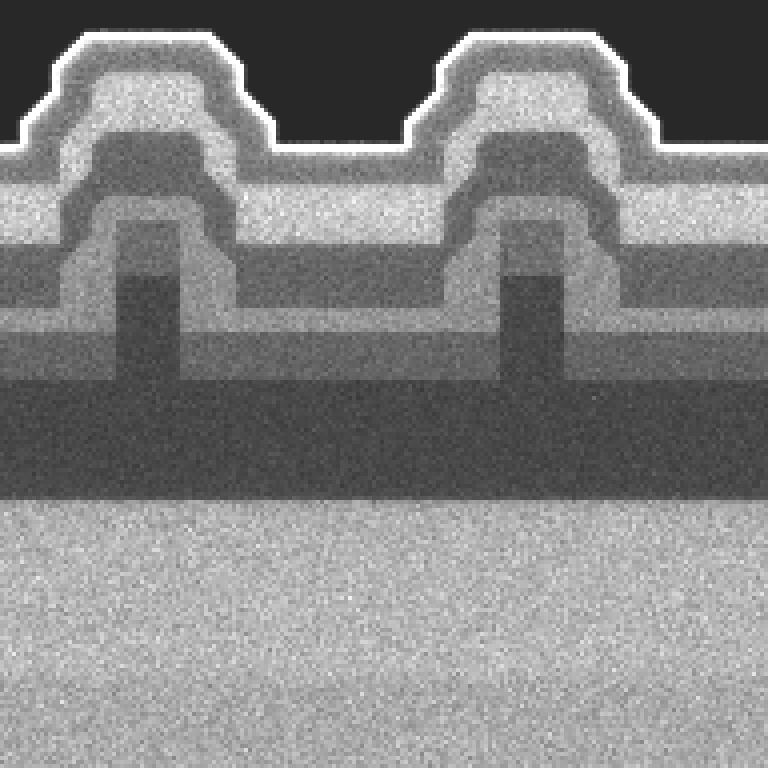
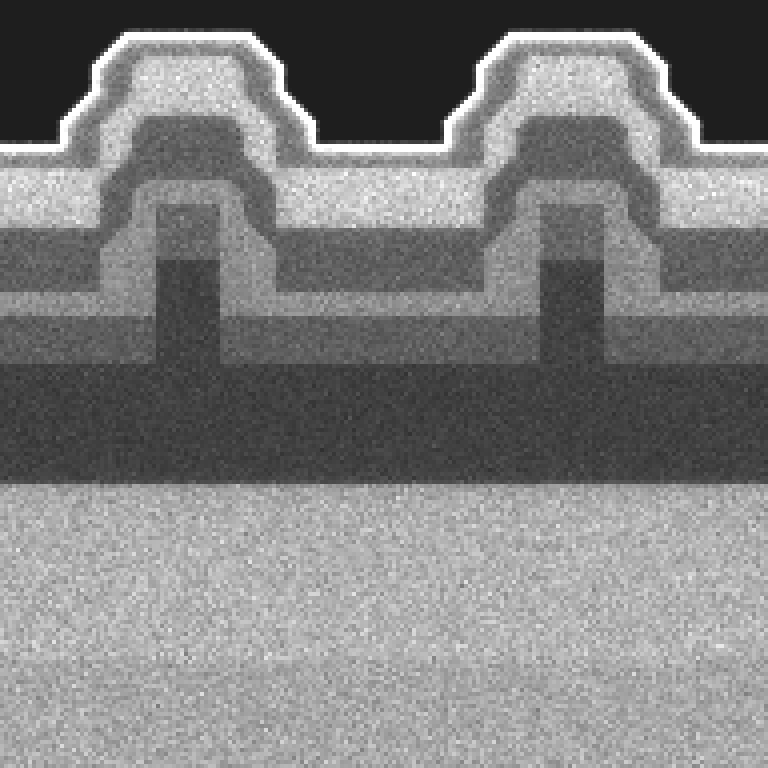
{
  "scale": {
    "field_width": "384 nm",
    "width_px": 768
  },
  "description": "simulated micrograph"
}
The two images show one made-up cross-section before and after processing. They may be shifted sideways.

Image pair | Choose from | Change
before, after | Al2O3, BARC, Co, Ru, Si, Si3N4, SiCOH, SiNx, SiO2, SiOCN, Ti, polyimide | Si3N4 (removed)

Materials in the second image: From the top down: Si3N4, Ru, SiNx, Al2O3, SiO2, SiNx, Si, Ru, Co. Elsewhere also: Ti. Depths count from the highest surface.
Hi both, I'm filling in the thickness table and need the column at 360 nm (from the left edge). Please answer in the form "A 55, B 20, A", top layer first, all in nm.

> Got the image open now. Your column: empty 56, Si3N4 12, Ru 30, SiNx 32, Al2O3 12, SiNx 24, Si 60, Ru 88, Co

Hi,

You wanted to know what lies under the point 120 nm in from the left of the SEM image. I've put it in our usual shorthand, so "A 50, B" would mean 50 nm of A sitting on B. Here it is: Si3N4 18, Ru 30, SiNx 32, Al2O3 30, SiO2 32, SiNx 24, Si 60, Ru 88, Co